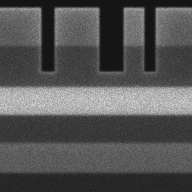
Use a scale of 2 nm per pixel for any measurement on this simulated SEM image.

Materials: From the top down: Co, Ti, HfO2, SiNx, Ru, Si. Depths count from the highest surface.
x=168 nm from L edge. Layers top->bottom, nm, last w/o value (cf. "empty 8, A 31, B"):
Co 76, Ti 82, HfO2 56, SiNx 56, Ru 60, Si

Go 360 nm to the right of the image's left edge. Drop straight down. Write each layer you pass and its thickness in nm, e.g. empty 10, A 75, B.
Co 76, Ti 82, HfO2 56, SiNx 56, Ru 60, Si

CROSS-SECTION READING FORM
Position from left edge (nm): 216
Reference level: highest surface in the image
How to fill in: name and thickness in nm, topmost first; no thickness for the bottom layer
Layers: empty 128, Ti 30, HfO2 56, SiNx 56, Ru 60, Si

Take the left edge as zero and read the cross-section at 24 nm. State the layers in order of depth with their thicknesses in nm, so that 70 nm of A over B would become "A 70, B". Co 76, Ti 82, HfO2 56, SiNx 56, Ru 60, Si